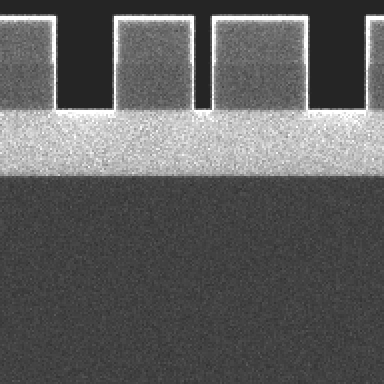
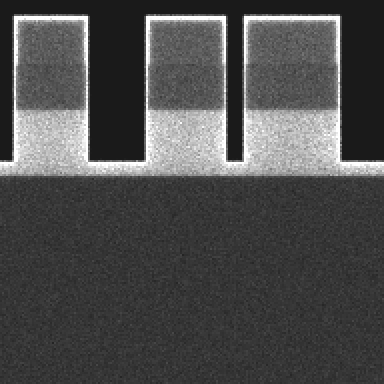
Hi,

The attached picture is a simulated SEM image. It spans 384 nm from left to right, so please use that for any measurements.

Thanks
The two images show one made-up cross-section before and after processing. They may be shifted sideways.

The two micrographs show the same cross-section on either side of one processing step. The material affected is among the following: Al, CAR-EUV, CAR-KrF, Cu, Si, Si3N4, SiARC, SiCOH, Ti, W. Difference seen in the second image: W removed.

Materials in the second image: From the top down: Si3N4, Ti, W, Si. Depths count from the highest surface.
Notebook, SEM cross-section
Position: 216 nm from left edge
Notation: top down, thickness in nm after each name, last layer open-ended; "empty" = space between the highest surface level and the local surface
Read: Si3N4 48, Ti 46, W 66, Si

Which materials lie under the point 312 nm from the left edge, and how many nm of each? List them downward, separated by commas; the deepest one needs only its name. Si3N4 48, Ti 46, W 66, Si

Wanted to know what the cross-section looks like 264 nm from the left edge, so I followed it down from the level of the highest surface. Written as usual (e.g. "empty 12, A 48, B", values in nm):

Si3N4 48, Ti 46, W 66, Si